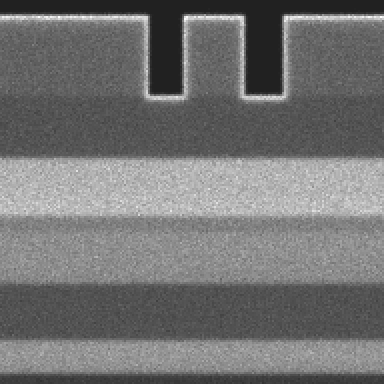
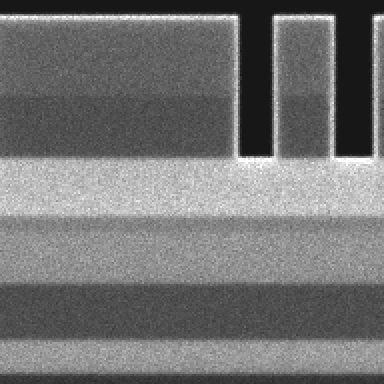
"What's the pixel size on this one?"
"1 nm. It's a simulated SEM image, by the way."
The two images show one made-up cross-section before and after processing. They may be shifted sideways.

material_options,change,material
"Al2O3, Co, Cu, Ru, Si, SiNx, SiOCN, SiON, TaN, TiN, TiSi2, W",removed,SiNx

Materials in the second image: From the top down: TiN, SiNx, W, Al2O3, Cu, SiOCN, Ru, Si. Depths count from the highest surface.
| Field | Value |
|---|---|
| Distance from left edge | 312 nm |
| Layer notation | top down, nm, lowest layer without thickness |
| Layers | TiN 80, SiNx 62, W 58, Al2O3 16, Cu 52, SiOCN 56, Ru 34, Si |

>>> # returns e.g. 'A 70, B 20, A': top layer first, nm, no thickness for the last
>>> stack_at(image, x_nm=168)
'TiN 80, SiNx 62, W 58, Al2O3 16, Cu 52, SiOCN 56, Ru 34, Si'